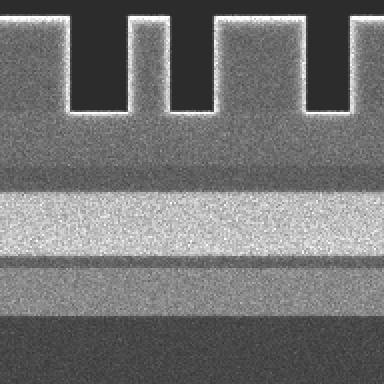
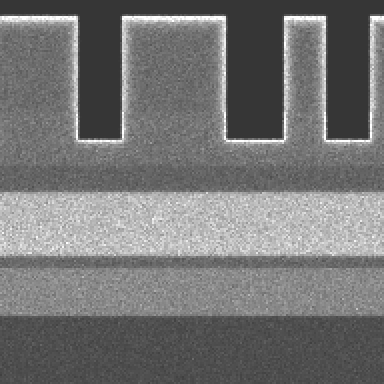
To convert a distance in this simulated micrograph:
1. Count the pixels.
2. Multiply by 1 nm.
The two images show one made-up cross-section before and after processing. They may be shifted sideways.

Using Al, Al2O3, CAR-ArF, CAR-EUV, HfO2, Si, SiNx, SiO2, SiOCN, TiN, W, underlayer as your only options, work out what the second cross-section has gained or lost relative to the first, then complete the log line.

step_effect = removed TiN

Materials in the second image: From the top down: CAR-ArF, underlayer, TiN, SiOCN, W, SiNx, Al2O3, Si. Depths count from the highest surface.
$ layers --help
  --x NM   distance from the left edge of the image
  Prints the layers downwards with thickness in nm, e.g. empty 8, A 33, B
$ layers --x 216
CAR-ArF 72, underlayer 24, TiN 54, SiOCN 26, W 64, SiNx 12, Al2O3 48, Si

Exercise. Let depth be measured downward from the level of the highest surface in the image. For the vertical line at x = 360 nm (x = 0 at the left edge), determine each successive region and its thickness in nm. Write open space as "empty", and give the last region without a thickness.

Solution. empty 124, TiN 26, SiOCN 26, W 64, SiNx 12, Al2O3 48, Si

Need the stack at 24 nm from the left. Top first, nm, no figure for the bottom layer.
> CAR-ArF 72, underlayer 24, TiN 54, SiOCN 26, W 64, SiNx 12, Al2O3 48, Si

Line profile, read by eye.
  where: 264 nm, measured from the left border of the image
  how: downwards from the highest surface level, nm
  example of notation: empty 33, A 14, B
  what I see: empty 124, TiN 26, SiOCN 26, W 64, SiNx 12, Al2O3 48, Si